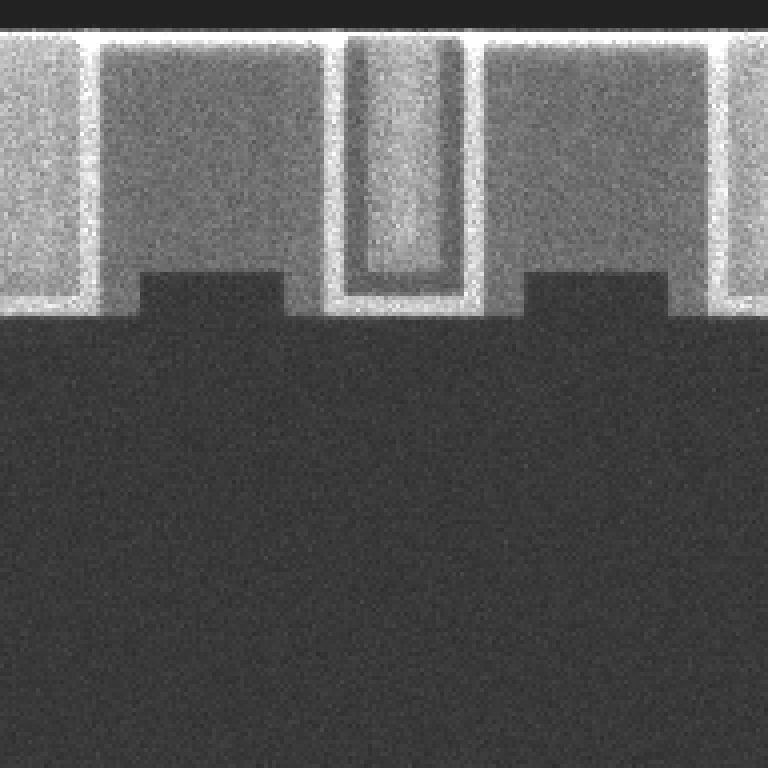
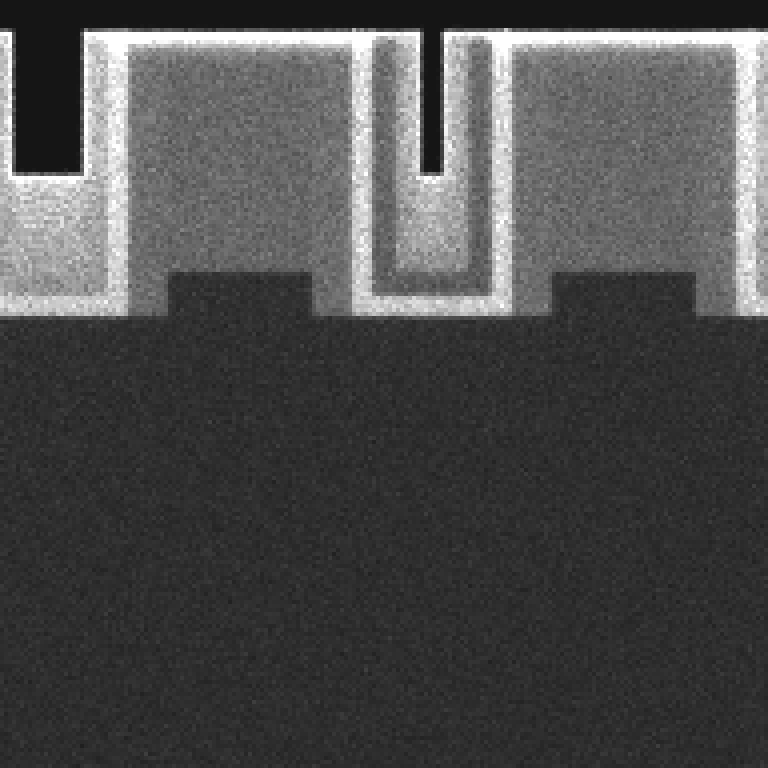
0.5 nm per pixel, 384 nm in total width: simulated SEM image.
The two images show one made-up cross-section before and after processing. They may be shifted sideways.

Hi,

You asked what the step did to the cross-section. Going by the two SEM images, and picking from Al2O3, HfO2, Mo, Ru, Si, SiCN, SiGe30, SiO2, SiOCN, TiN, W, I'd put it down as W, removed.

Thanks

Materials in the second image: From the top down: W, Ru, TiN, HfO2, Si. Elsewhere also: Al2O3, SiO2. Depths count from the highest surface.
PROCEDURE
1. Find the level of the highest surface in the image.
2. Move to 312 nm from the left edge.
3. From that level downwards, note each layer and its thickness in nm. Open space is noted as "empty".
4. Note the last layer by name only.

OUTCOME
SiO2 120, Si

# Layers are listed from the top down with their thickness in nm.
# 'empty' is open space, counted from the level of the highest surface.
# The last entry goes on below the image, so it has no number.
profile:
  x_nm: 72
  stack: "Al2O3 142, Si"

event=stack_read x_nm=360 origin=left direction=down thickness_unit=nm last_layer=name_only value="Al2O3 142, Si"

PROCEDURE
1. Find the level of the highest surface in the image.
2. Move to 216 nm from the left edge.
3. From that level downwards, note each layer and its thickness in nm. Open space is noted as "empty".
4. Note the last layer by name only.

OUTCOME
empty 72, W 36, Ru 12, TiN 12, HfO2 10, Si